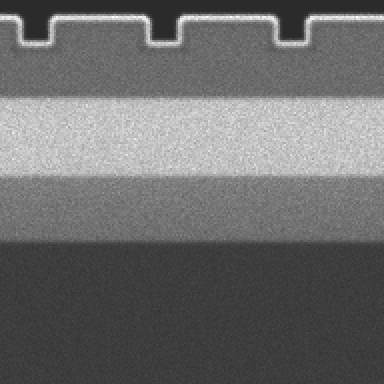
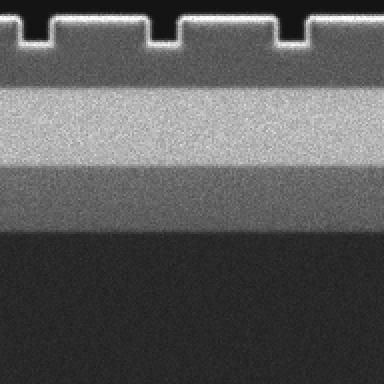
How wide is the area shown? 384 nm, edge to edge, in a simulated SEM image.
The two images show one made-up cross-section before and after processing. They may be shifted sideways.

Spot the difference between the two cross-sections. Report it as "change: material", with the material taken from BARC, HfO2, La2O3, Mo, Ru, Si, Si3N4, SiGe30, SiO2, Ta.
removed: Si3N4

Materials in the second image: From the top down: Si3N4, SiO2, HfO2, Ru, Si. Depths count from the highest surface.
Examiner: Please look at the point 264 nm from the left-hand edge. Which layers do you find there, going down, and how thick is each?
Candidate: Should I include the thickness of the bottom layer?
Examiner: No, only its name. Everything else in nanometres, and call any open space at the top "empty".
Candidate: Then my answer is SiO2 72, HfO2 78, Ru 66, Si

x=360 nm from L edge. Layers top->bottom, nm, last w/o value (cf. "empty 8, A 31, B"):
SiO2 72, HfO2 78, Ru 66, Si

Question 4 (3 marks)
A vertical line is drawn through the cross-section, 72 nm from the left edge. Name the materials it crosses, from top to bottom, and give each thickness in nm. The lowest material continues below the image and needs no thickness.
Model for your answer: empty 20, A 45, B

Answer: SiO2 72, HfO2 78, Ru 66, Si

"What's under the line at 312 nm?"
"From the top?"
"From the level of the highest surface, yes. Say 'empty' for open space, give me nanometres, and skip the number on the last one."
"Si3N4 26, SiO2 46, HfO2 78, Ru 66, Si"